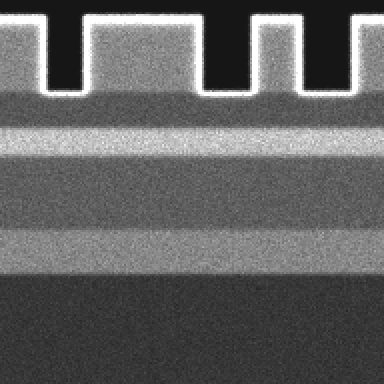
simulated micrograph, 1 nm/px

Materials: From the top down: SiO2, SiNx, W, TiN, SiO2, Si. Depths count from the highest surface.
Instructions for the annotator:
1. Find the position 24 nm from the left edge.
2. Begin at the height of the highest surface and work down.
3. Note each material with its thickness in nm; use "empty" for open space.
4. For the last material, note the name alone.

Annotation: SiO2 76, SiNx 36, W 28, TiN 74, SiO2 44, Si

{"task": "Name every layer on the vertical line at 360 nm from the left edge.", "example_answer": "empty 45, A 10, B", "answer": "SiO2 76, SiNx 36, W 28, TiN 74, SiO2 44, Si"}